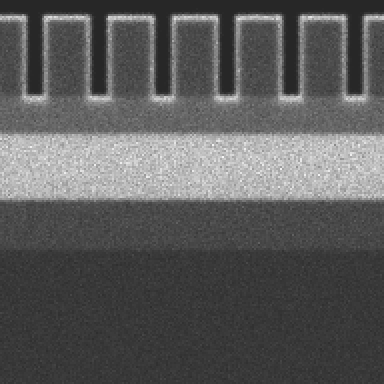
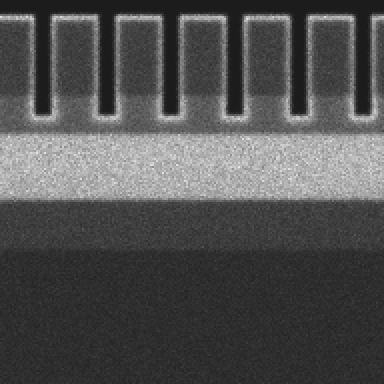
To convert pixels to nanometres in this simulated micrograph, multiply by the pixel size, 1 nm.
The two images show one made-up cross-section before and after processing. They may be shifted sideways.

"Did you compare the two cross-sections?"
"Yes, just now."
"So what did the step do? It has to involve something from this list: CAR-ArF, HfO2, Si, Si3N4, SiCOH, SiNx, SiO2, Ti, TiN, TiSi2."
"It removed SiO2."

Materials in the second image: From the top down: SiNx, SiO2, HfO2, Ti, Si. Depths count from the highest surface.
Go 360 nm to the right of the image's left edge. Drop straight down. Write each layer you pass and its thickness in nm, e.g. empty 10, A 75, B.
empty 100, SiO2 18, HfO2 66, Ti 50, Si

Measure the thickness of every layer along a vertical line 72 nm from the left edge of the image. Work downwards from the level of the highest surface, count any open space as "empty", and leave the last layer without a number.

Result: SiNx 80, SiO2 38, HfO2 66, Ti 50, Si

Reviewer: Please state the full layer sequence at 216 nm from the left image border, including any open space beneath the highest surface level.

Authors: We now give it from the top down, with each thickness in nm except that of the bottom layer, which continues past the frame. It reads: SiNx 80, SiO2 38, HfO2 66, Ti 50, Si